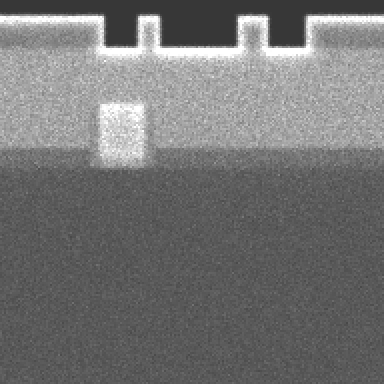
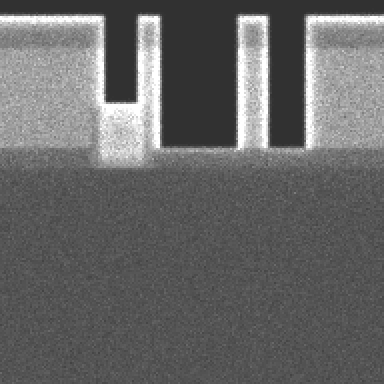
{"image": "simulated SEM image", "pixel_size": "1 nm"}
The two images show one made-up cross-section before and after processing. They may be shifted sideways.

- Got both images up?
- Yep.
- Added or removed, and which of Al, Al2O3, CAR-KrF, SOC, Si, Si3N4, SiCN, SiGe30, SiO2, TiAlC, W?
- removed, SiO2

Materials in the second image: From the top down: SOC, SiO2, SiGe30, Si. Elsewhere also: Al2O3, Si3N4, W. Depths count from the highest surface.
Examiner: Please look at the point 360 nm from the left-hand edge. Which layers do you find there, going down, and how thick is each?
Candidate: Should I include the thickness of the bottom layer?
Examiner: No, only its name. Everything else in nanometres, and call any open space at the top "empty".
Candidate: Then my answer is SOC 32, SiO2 100, SiGe30 20, Si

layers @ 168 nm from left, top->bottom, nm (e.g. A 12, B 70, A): empty 132, SiGe30 20, Si